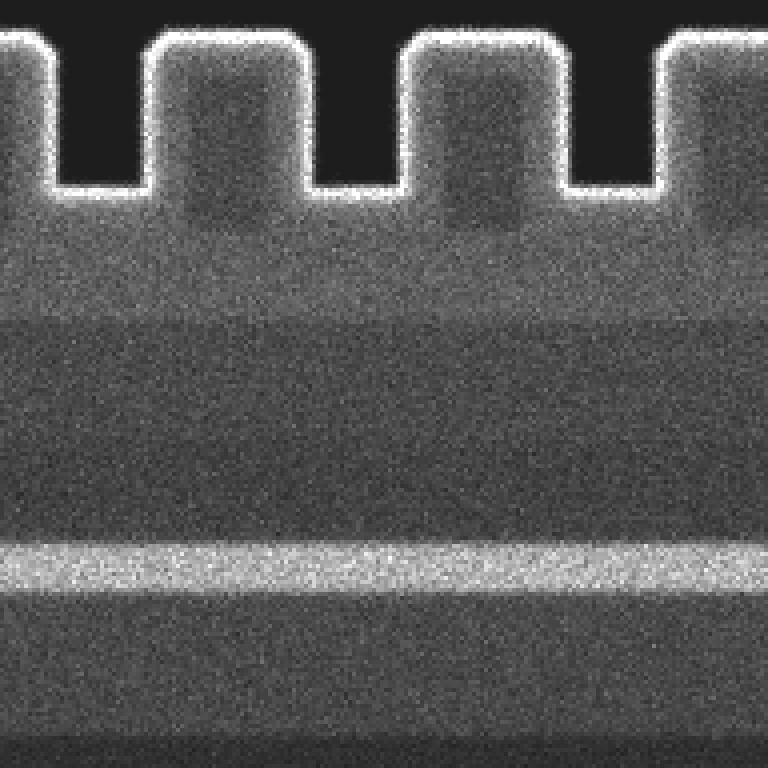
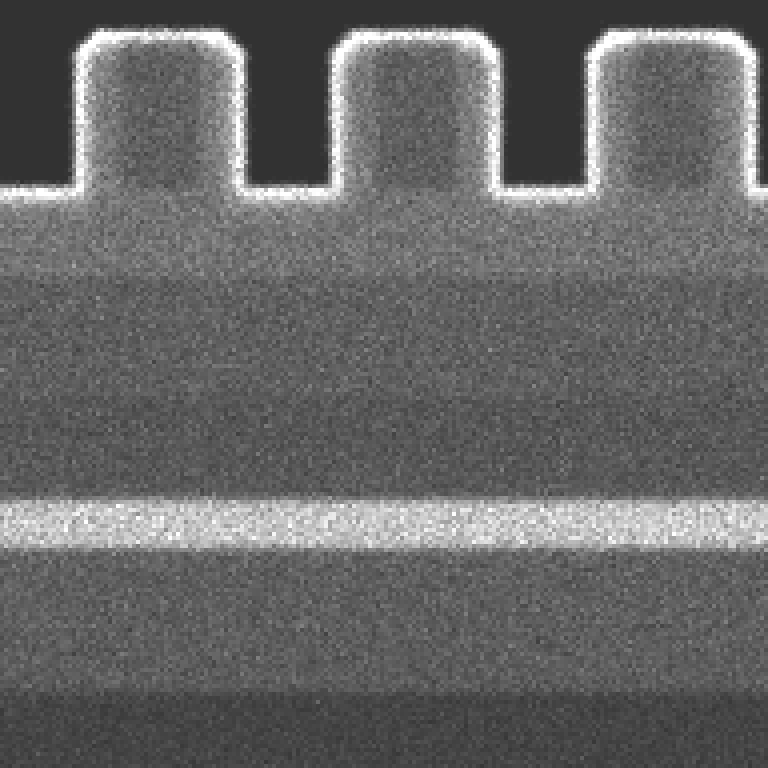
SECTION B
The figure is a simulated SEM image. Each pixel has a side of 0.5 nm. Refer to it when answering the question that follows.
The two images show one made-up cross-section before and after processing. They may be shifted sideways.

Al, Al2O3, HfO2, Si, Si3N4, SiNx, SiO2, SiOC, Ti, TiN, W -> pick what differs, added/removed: Al2O3 removed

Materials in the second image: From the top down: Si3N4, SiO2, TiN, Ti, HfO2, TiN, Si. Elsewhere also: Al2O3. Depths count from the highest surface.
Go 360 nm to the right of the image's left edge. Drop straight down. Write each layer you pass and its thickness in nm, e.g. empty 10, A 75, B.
Al2O3 78, SiO2 44, TiN 60, Ti 52, HfO2 24, TiN 72, Si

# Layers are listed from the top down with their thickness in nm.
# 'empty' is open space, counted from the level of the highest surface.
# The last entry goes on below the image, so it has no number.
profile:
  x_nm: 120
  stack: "empty 10, Al2O3 68, SiO2 44, TiN 60, Ti 52, HfO2 24, TiN 72, Si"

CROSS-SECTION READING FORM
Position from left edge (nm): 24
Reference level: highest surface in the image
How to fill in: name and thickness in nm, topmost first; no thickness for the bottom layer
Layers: empty 78, SiO2 44, TiN 60, Ti 52, HfO2 24, TiN 72, Si